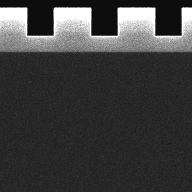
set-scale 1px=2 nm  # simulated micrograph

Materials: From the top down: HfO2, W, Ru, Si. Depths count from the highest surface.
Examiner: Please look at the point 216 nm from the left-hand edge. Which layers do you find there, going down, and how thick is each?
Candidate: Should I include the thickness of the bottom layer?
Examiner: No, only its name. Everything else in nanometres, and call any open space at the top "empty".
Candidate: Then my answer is empty 56, Ru 32, Si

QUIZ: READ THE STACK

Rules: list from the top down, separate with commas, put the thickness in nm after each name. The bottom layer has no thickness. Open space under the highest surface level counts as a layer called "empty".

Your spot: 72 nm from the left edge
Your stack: empty 56, Ru 32, Si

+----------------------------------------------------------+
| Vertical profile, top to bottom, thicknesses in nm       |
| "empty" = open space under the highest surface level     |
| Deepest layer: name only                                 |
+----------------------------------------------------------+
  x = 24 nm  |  HfO2 24, W 24, Ru 40, Si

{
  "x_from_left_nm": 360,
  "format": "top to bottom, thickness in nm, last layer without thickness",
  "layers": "empty 56, Ru 32, Si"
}